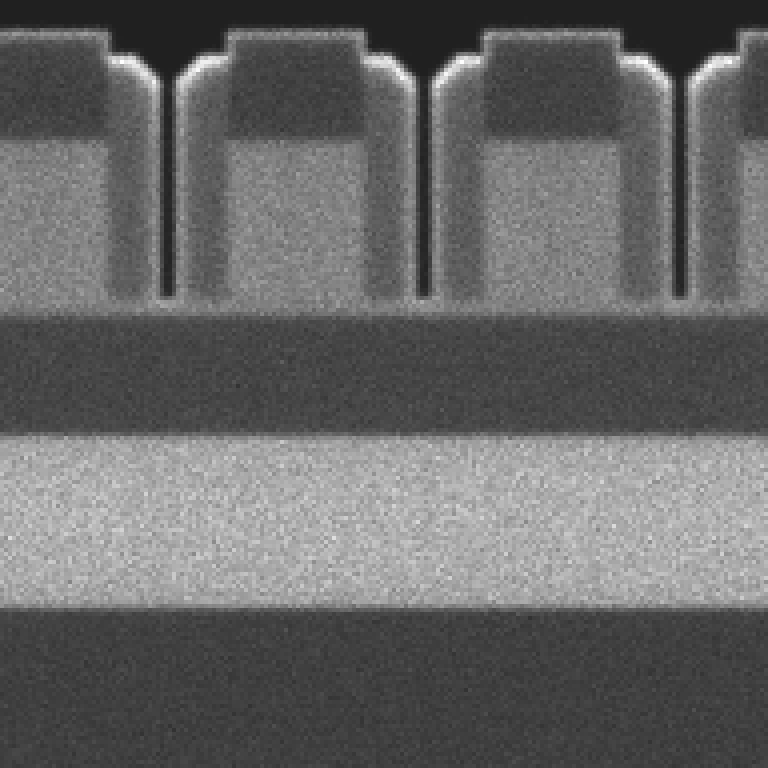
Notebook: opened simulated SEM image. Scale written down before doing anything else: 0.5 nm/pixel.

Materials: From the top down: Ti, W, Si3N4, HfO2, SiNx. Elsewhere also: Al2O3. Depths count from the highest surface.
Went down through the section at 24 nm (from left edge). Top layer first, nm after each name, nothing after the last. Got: Ti 54, W 88, Si3N4 60, HfO2 86, SiNx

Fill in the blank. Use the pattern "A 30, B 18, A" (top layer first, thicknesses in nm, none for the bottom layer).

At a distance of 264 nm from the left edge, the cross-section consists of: Ti 54, W 88, Si3N4 60, HfO2 86, SiNx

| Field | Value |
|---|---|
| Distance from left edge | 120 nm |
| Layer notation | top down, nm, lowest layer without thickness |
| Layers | Ti 54, W 88, Si3N4 60, HfO2 86, SiNx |